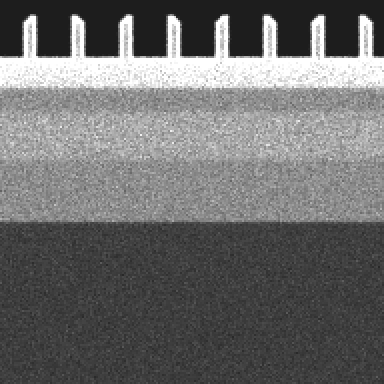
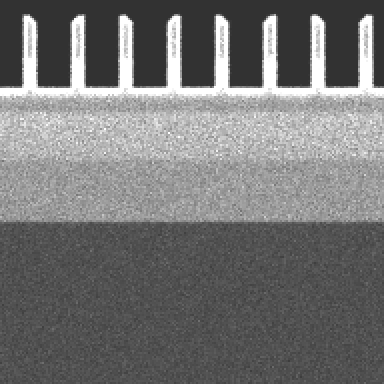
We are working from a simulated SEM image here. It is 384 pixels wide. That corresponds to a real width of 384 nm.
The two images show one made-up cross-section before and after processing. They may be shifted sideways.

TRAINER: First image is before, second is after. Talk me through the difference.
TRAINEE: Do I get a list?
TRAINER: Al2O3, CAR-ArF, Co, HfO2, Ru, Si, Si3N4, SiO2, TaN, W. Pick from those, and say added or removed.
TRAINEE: removed: W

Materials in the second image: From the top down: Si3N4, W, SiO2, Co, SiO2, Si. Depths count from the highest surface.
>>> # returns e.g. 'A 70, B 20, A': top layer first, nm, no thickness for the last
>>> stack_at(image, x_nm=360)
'empty 6, Si3N4 36, W 30, SiO2 24, Co 48, SiO2 62, Si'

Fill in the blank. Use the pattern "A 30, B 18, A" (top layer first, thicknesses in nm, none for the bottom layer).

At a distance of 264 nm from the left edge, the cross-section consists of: empty 6, Si3N4 36, W 30, SiO2 24, Co 48, SiO2 62, Si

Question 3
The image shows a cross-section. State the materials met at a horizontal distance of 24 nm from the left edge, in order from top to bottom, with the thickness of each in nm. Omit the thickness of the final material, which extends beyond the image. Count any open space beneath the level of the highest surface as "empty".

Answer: Si3N4 42, W 30, SiO2 24, Co 48, SiO2 62, Si